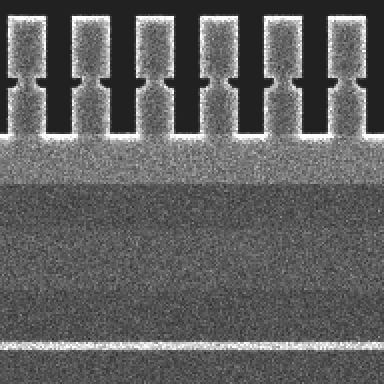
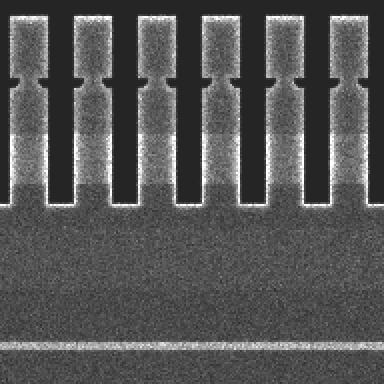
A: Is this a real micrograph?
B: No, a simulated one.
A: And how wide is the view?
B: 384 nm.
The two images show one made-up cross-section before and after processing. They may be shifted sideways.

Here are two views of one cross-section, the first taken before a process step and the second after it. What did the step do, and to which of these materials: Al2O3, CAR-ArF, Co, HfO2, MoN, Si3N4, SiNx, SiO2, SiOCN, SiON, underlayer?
It removed SiNx and SiO2.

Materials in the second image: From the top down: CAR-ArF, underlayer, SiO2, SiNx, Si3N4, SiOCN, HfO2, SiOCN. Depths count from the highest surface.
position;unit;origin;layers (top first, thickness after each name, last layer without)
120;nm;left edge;empty 188, SiNx 24, Si3N4 62, SiOCN 52, HfO2 8, SiOCN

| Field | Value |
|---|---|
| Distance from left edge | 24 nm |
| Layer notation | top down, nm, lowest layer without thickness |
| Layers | CAR-ArF 62, underlayer 56, SiO2 50, SiNx 44, Si3N4 62, SiOCN 52, HfO2 8, SiOCN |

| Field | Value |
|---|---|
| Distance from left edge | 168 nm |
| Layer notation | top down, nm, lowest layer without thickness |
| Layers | CAR-ArF 62, empty 8, underlayer 48, SiO2 50, SiNx 44, Si3N4 62, SiOCN 52, HfO2 8, SiOCN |